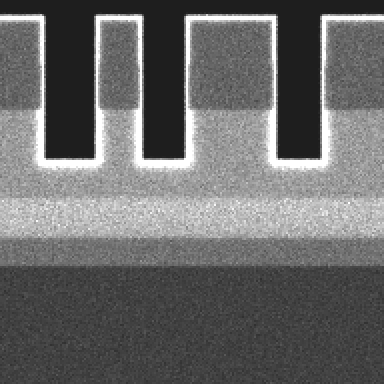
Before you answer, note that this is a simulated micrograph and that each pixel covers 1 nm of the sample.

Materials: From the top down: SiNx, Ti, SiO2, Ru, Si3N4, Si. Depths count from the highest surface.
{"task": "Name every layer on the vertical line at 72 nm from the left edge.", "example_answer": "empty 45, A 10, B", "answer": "empty 144, SiO2 38, Ru 40, Si3N4 28, Si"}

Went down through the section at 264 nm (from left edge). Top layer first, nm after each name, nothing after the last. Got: SiNx 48, Ti 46, SiO2 88, Ru 40, Si3N4 28, Si